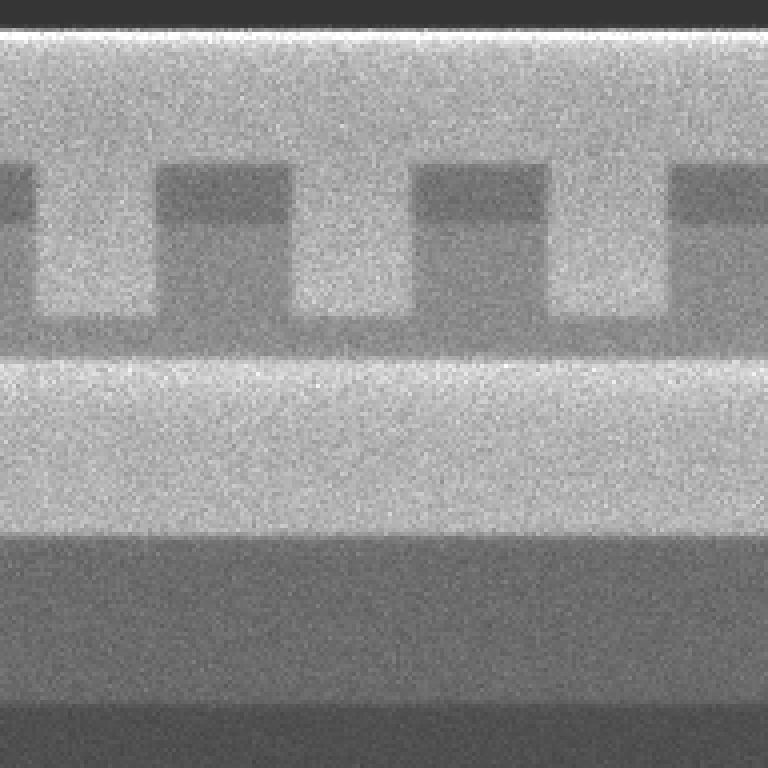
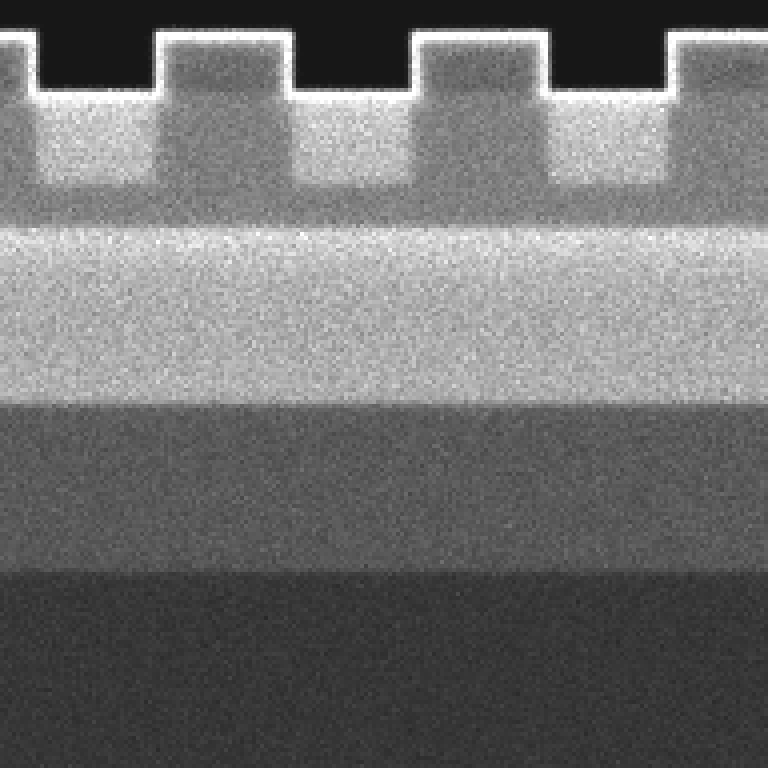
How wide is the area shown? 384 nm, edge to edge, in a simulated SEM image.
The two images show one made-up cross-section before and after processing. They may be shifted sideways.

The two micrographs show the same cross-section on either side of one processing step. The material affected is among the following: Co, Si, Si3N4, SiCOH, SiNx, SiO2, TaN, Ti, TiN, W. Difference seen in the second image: Co removed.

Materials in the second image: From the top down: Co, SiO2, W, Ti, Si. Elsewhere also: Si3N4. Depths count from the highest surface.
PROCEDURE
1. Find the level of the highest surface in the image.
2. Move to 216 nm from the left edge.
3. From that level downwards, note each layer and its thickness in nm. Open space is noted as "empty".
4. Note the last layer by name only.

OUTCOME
Si3N4 30, SiO2 68, W 88, Ti 84, Si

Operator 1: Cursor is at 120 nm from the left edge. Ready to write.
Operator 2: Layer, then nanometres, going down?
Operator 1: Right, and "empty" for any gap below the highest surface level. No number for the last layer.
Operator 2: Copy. Si3N4 30, SiO2 68, W 88, Ti 84, Si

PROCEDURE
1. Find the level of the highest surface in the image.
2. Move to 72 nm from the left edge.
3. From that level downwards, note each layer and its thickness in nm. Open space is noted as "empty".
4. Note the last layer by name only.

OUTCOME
empty 30, Co 46, SiO2 22, W 88, Ti 84, Si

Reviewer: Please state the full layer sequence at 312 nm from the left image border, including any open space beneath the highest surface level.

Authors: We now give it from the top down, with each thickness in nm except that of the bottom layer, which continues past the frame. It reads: empty 30, Co 46, SiO2 22, W 88, Ti 84, Si